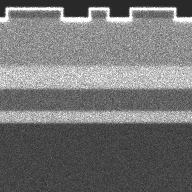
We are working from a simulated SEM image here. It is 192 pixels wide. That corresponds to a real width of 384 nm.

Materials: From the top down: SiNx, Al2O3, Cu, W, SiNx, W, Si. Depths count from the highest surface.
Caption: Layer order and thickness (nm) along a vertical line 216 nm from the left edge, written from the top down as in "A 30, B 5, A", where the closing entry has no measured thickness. SiNx 20, Al2O3 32, Cu 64, W 46, SiNx 44, W 24, Si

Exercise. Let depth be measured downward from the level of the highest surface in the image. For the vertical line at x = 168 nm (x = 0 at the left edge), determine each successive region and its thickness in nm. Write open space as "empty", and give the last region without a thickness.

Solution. empty 20, Al2O3 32, Cu 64, W 46, SiNx 44, W 24, Si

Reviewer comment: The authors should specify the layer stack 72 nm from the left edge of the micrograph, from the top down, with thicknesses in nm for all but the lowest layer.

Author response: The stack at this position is SiNx 20, Al2O3 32, Cu 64, W 46, SiNx 44, W 24, Si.